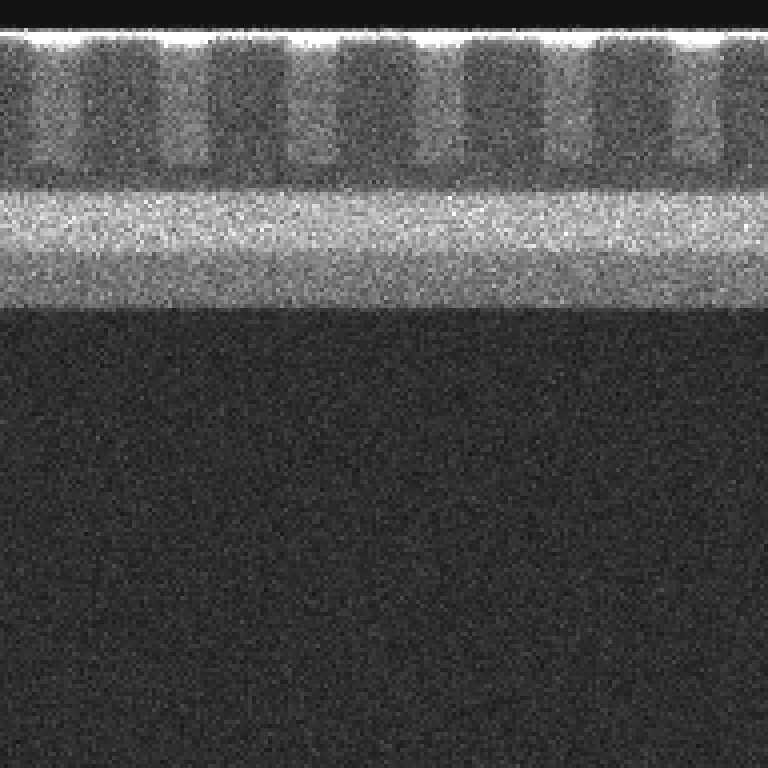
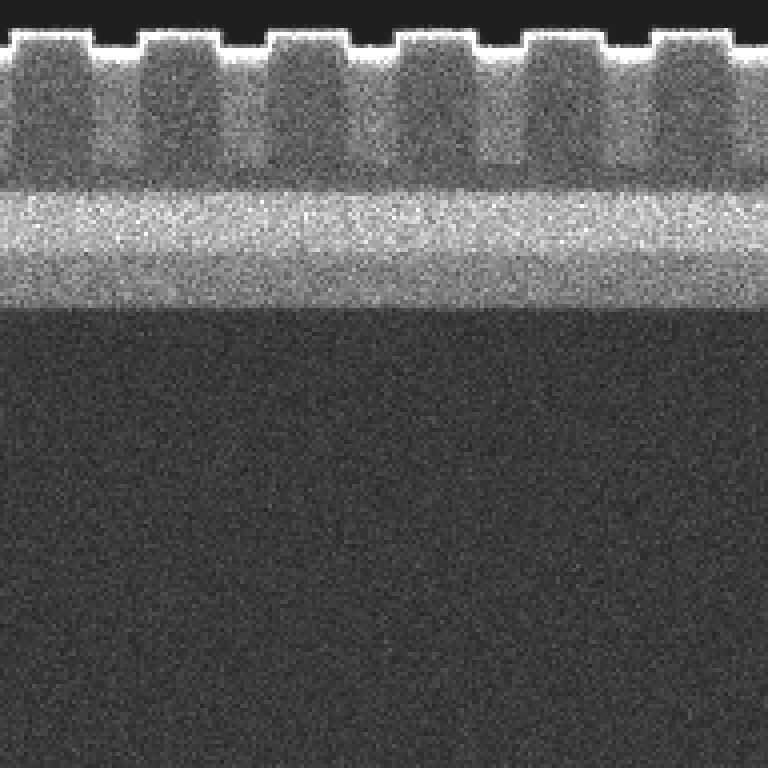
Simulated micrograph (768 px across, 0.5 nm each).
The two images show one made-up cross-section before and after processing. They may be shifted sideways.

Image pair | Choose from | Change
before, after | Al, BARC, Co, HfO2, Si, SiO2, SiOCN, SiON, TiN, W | SiO2 (removed)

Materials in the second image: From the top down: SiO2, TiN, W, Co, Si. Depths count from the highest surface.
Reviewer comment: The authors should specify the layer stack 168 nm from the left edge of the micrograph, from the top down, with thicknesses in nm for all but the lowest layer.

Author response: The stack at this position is TiN 80, W 30, Co 28, Si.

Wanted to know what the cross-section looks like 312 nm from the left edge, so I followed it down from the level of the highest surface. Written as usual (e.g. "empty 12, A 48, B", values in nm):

empty 8, SiO2 58, TiN 14, W 30, Co 28, Si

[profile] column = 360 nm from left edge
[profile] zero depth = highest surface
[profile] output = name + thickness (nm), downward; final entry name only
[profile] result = TiN 80, W 30, Co 28, Si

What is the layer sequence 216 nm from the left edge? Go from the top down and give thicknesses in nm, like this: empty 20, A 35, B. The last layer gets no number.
TiN 80, W 30, Co 28, Si